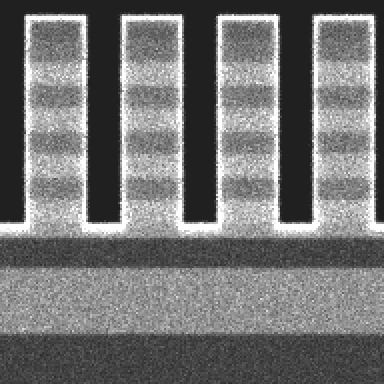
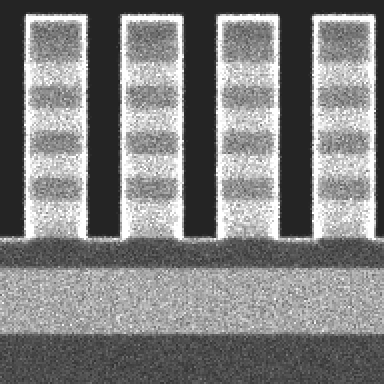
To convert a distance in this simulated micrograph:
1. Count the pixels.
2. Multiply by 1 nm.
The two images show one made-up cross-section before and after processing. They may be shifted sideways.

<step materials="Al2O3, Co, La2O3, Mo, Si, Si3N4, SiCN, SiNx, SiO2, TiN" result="removed Al2O3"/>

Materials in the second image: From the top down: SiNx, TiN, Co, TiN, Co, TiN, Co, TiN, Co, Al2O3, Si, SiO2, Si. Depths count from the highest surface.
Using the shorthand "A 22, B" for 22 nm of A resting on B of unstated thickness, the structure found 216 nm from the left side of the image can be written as empty 222, Si 30, SiO2 66, Si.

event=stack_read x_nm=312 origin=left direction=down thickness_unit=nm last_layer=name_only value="empty 222, Si 30, SiO2 66, Si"